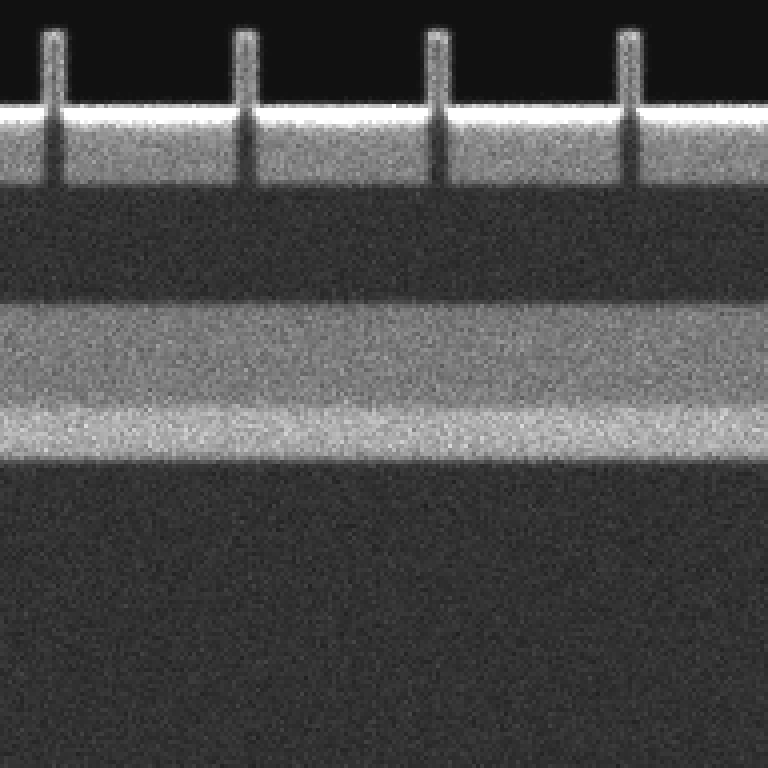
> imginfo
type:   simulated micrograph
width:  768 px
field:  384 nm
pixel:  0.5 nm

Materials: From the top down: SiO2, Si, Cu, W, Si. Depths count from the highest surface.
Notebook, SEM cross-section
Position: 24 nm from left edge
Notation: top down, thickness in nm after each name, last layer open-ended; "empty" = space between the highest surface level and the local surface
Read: Si 136, Cu 52, W 26, Si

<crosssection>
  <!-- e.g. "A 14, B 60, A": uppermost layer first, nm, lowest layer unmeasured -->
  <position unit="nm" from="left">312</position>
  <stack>Si 136, Cu 52, W 26, Si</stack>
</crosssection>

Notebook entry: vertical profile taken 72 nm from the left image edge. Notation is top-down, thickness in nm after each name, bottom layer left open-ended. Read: empty 38, SiO2 38, Si 60, Cu 52, W 26, Si